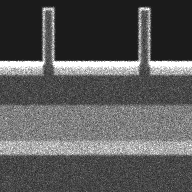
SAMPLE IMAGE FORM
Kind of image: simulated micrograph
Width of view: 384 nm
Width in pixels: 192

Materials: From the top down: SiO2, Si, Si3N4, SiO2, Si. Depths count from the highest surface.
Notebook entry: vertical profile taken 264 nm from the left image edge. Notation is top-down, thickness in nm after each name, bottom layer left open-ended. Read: empty 108, SiO2 26, Si 60, Si3N4 72, SiO2 28, Si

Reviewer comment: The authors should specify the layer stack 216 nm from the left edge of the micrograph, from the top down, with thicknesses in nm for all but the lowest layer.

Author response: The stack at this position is empty 108, SiO2 26, Si 60, Si3N4 72, SiO2 28, Si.